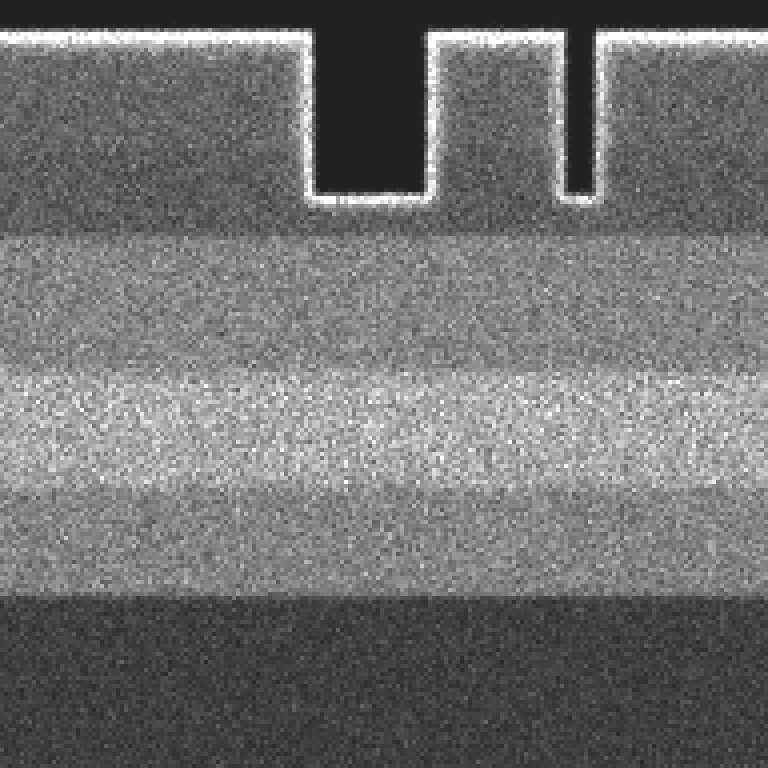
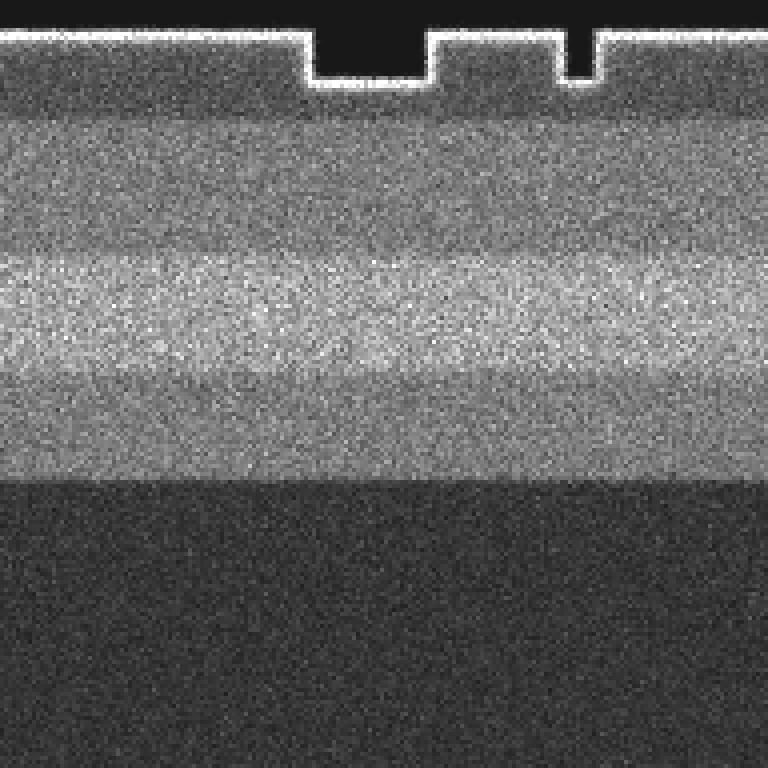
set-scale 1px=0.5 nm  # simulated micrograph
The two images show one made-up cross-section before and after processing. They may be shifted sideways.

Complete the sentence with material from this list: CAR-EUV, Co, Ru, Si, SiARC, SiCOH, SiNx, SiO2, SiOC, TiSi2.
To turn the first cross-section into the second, SiARC must be removed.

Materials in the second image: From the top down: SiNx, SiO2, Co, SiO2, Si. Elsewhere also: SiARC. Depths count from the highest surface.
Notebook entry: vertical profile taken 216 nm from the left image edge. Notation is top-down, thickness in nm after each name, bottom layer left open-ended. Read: SiNx 44, SiO2 68, Co 58, SiO2 54, Si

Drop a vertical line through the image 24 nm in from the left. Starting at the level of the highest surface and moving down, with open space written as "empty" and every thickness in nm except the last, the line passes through SiNx 44, SiO2 68, Co 58, SiO2 54, Si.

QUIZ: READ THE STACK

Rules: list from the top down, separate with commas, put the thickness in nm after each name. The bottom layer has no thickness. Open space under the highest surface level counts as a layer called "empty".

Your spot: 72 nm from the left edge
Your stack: SiNx 44, SiO2 68, Co 58, SiO2 54, Si